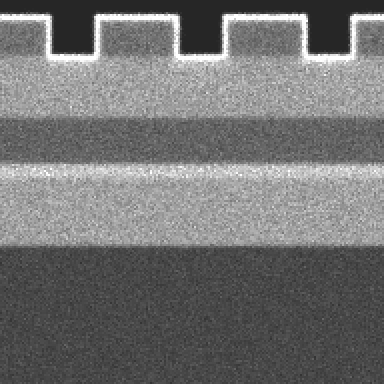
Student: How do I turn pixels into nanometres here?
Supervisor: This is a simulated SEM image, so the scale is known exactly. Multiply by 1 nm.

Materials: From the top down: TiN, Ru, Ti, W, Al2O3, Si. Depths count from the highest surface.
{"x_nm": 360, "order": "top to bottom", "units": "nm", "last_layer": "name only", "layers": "TiN 40, Ru 62, Ti 46, W 14, Al2O3 68, Si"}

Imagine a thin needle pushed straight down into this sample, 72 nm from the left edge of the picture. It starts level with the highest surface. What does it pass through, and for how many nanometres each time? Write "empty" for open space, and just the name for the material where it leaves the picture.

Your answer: empty 40, Ru 62, Ti 46, W 14, Al2O3 68, Si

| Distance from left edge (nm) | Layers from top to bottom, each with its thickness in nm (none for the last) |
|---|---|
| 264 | TiN 40, Ru 62, Ti 46, W 14, Al2O3 68, Si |